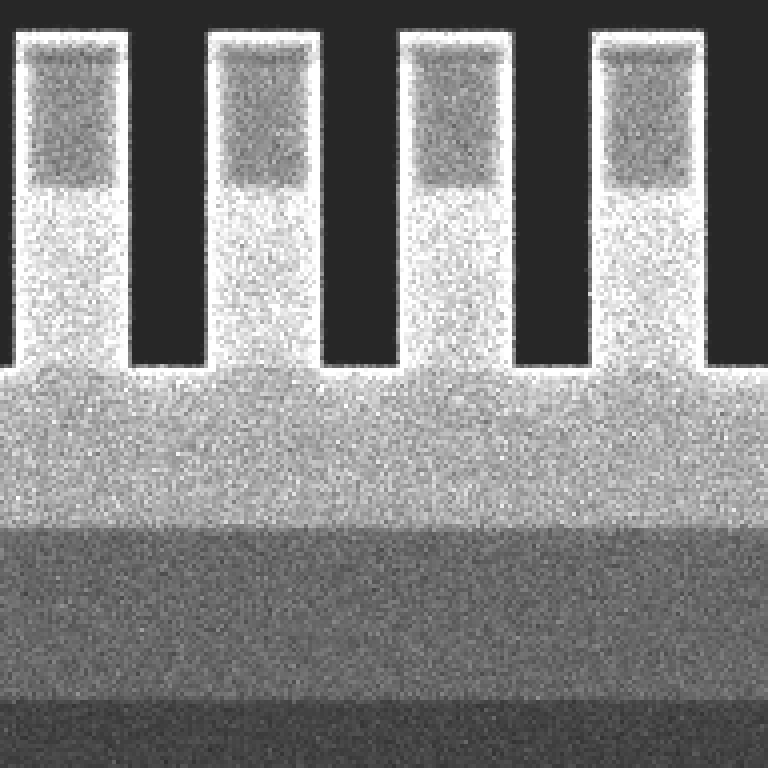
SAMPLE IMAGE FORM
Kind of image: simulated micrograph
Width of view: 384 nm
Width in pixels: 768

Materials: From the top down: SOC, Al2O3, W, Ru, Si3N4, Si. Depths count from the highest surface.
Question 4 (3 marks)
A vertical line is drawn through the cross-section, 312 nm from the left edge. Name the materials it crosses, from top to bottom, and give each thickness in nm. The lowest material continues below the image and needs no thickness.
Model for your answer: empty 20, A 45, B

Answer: SOC 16, Al2O3 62, W 90, Ru 80, Si3N4 86, Si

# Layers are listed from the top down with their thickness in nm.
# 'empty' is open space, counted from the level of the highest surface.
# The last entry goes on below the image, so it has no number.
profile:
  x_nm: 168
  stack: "empty 168, Ru 80, Si3N4 86, Si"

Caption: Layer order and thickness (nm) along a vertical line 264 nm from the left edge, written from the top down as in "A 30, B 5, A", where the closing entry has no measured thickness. empty 168, Ru 80, Si3N4 86, Si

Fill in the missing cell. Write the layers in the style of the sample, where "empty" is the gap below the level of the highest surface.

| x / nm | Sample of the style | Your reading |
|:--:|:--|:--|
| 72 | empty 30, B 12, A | empty 168, Ru 80, Si3N4 86, Si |